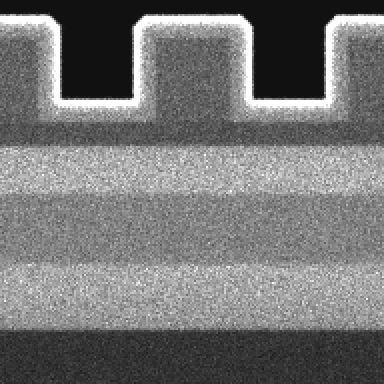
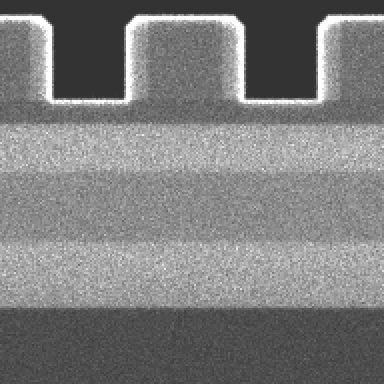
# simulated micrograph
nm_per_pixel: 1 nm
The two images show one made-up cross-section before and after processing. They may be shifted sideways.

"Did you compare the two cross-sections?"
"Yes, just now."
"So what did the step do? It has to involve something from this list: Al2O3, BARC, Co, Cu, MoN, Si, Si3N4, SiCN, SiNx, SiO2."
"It removed Al2O3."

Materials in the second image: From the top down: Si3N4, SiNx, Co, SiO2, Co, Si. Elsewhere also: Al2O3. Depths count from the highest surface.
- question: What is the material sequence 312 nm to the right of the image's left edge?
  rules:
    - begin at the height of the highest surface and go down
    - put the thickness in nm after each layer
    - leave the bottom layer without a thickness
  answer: empty 84, SiNx 24, Co 48, SiO2 70, Co 66, Si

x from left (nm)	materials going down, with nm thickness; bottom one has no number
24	Si3N4 84, SiNx 24, Co 48, SiO2 70, Co 66, Si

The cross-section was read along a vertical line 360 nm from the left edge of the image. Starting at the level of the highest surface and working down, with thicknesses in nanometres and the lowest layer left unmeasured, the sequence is Si3N4 84, SiNx 24, Co 48, SiO2 70, Co 66, Si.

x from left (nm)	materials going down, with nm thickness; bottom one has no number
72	empty 84, SiNx 24, Co 48, SiO2 70, Co 66, Si